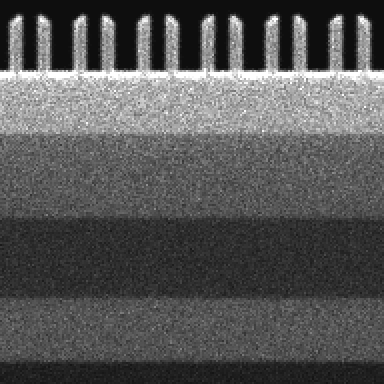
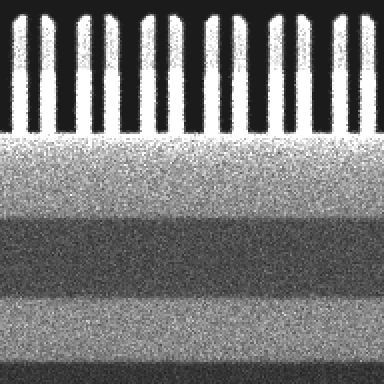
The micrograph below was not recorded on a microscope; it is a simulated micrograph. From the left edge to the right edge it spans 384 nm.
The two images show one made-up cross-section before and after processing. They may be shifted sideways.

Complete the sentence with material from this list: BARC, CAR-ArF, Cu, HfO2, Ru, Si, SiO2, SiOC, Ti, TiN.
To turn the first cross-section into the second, HfO2 must be removed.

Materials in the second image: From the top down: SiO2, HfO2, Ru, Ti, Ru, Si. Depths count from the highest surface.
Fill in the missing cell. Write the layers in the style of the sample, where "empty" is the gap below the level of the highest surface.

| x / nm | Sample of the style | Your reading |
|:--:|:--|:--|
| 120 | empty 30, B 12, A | empty 118, Ru 84, Ti 80, Ru 64, Si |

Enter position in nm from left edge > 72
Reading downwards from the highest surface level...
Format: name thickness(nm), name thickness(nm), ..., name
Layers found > empty 118, Ru 84, Ti 80, Ru 64, Si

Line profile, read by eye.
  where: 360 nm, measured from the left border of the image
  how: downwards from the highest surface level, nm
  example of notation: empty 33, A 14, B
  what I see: empty 118, Ru 84, Ti 80, Ru 64, Si